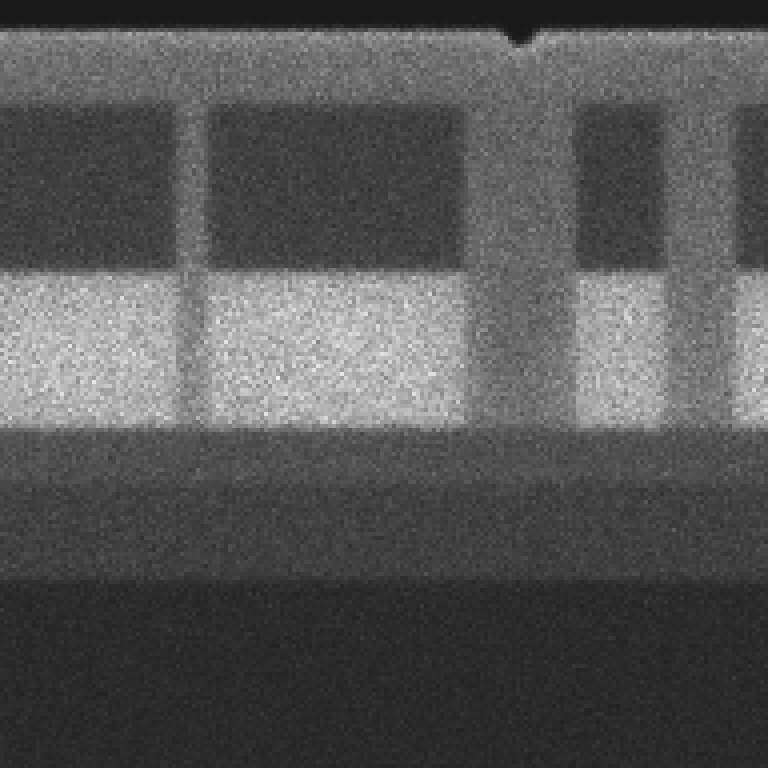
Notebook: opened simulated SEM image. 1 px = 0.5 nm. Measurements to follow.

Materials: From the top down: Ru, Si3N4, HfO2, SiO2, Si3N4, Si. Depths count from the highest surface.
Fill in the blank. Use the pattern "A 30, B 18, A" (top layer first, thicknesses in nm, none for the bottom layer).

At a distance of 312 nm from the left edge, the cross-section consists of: Ru 36, Si3N4 84, HfO2 78, SiO2 28, Si3N4 48, Si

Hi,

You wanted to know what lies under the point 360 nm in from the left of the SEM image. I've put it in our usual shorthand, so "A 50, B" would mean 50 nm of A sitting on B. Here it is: Ru 198, SiO2 28, Si3N4 48, Si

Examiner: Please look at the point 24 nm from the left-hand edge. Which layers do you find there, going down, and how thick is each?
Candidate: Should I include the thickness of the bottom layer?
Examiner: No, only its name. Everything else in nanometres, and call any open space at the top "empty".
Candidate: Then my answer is Ru 36, Si3N4 84, HfO2 78, SiO2 28, Si3N4 48, Si